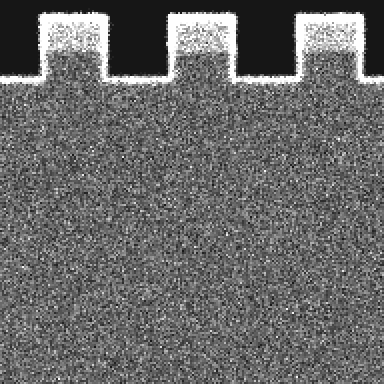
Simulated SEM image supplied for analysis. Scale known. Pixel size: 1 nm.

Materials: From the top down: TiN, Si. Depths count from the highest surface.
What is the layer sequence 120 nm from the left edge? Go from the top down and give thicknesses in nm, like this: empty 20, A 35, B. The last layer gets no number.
empty 62, Si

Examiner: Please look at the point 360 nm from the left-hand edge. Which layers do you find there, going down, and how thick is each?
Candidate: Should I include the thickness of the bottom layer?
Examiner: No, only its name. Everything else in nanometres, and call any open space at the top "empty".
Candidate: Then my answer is TiN 36, Si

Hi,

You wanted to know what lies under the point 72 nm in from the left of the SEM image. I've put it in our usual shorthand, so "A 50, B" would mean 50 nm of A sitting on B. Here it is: TiN 36, Si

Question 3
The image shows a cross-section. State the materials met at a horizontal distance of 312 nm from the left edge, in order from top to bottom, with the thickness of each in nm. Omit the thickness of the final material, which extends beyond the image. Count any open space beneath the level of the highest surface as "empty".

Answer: TiN 36, Si